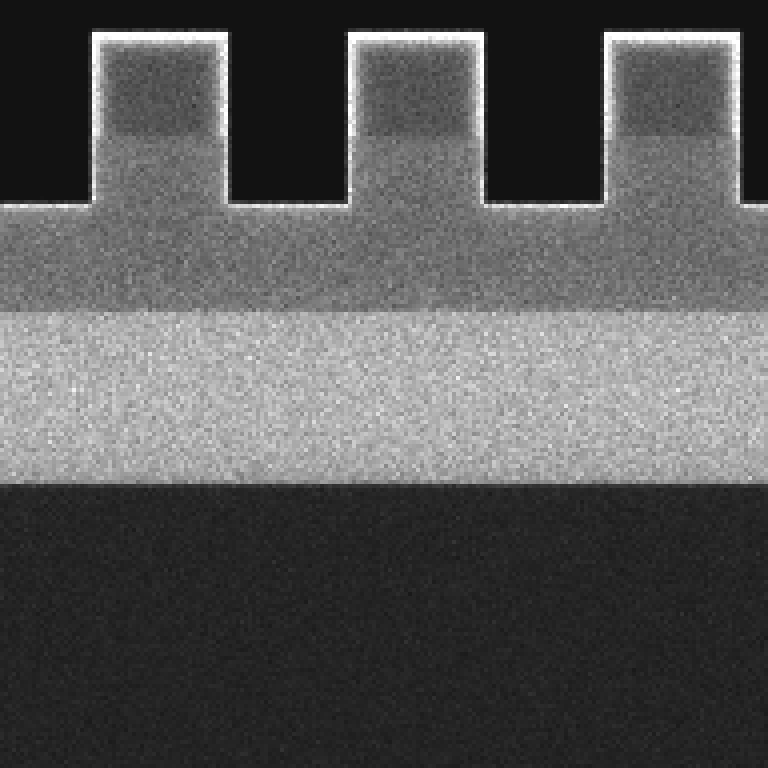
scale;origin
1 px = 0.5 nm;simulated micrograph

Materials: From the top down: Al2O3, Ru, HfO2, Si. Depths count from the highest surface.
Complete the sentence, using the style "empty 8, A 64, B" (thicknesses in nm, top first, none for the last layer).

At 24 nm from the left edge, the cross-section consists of empty 86, Ru 54, HfO2 86, Si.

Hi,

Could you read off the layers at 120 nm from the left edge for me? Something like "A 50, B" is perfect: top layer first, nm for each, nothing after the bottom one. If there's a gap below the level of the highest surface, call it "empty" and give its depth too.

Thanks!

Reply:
empty 86, Ru 54, HfO2 86, Si